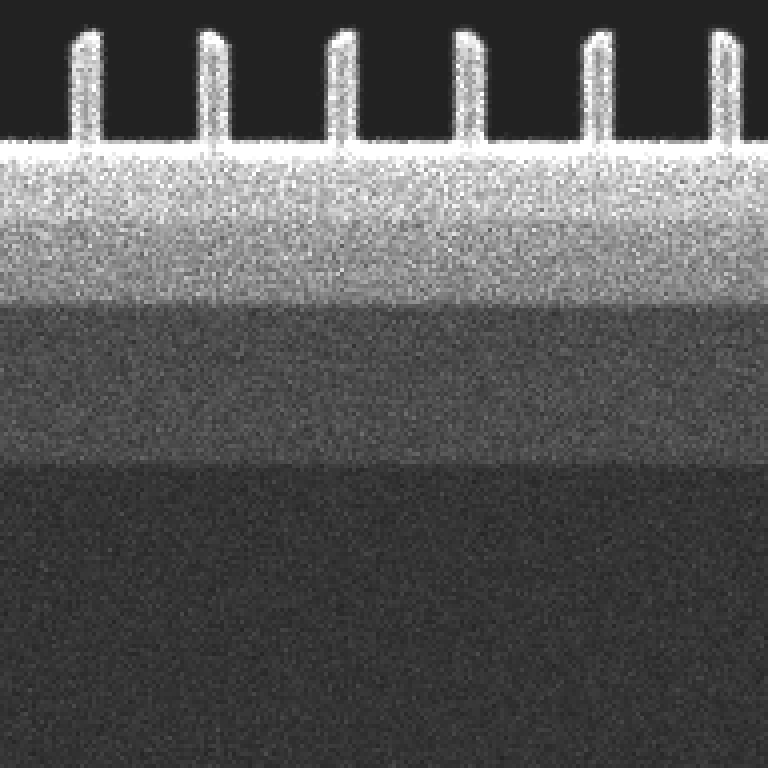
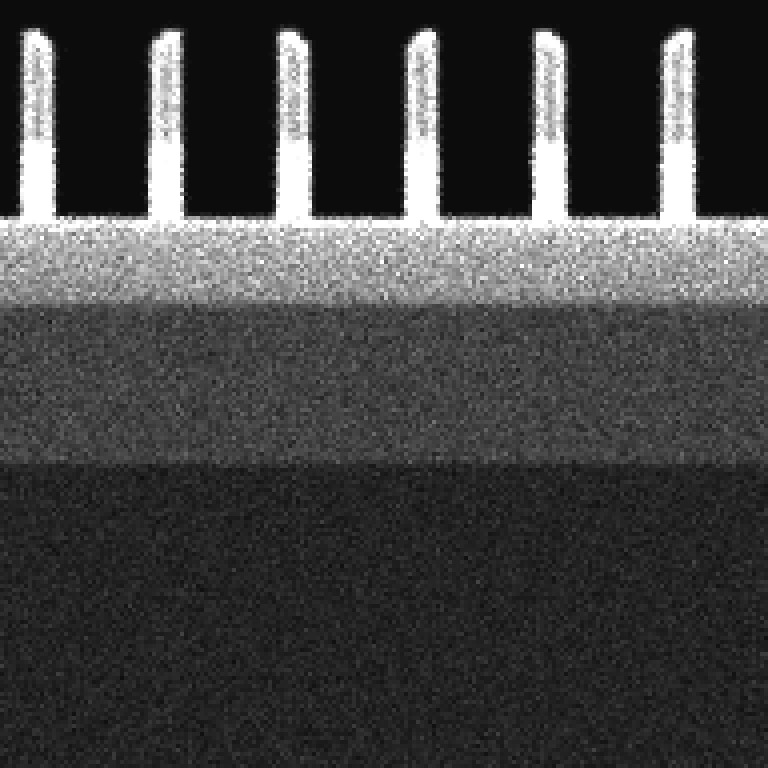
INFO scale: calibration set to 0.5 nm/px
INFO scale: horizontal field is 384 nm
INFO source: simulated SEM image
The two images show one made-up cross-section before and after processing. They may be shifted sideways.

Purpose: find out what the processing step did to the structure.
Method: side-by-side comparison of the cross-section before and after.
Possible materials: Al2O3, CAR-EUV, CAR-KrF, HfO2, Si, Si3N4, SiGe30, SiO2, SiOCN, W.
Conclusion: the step removed HfO2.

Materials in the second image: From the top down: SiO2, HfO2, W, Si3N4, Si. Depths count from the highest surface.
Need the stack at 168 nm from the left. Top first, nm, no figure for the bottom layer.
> empty 94, W 42, Si3N4 80, Si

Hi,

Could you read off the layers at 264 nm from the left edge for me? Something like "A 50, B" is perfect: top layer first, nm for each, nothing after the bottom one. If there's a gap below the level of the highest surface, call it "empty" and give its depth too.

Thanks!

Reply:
empty 94, W 42, Si3N4 80, Si